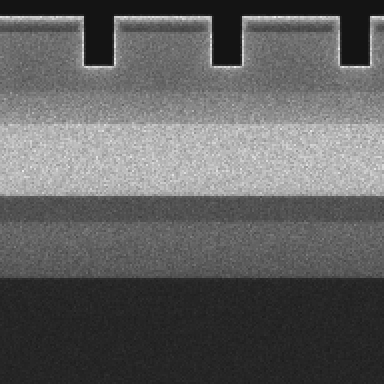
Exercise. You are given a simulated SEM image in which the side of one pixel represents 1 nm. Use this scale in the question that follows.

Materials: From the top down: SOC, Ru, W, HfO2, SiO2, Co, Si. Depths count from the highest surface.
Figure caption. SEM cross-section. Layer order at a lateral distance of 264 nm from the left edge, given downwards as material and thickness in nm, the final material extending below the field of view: SOC 16, Ru 60, W 32, HfO2 72, SiO2 26, Co 56, Si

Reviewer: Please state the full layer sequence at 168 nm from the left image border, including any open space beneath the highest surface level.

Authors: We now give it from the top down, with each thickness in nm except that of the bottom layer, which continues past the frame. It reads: SOC 16, Ru 60, W 32, HfO2 72, SiO2 26, Co 56, Si